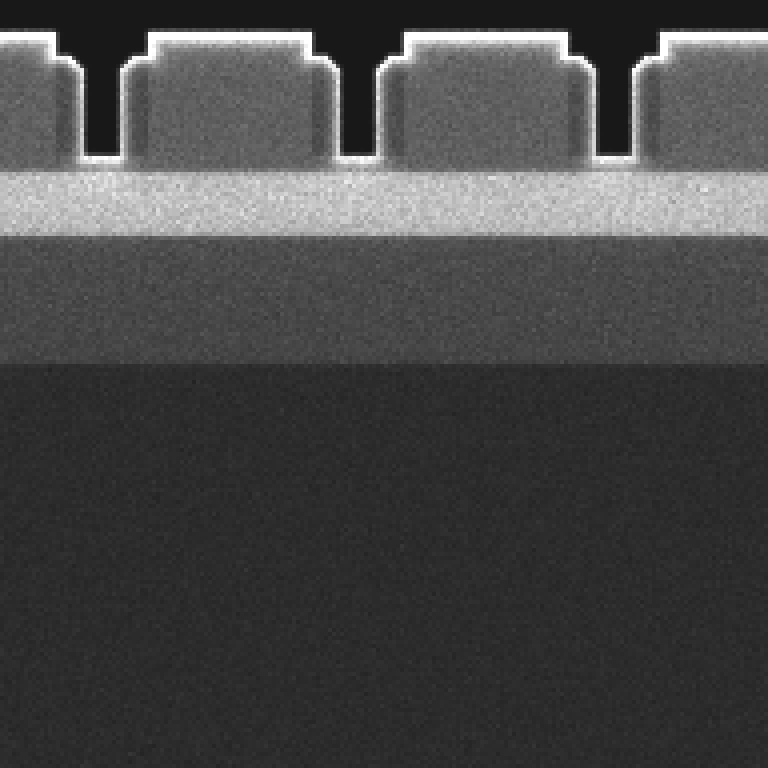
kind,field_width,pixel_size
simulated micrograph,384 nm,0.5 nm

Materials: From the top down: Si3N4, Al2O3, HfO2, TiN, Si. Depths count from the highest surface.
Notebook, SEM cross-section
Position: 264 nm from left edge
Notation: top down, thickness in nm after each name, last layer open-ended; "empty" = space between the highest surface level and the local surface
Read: Al2O3 70, HfO2 32, TiN 64, Si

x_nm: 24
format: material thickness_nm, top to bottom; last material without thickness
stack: Al2O3 70, HfO2 32, TiN 64, Si